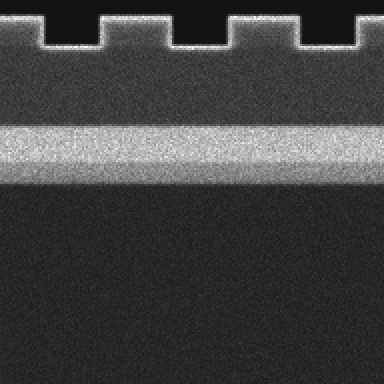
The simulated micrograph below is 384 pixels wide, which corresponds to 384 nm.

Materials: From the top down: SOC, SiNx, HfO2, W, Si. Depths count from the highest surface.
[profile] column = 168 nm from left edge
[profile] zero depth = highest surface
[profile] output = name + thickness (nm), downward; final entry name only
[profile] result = SOC 30, SiNx 80, HfO2 36, W 22, Si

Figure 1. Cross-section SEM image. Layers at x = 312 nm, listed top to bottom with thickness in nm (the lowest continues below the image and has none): empty 30, SiNx 80, HfO2 36, W 22, Si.